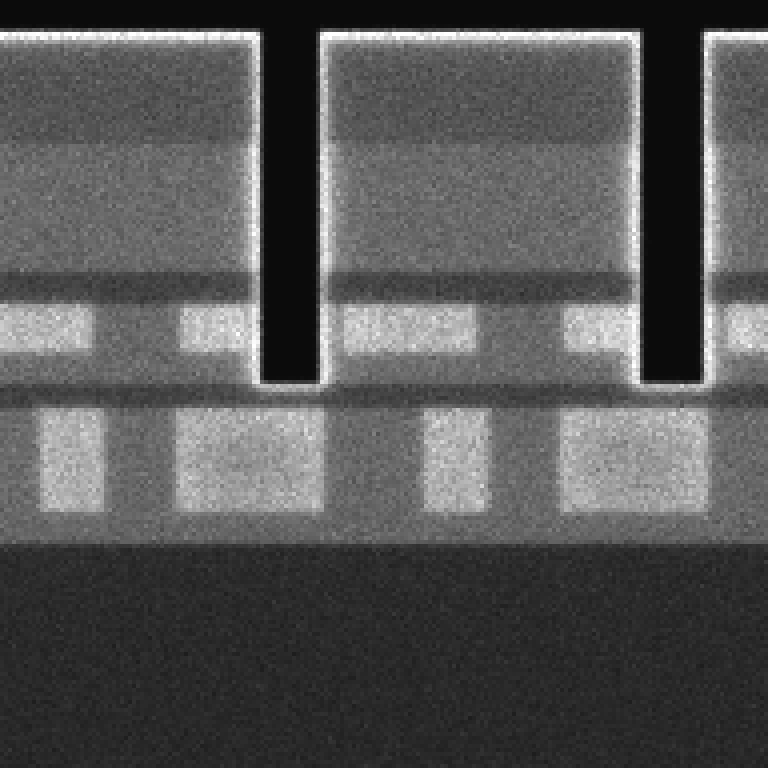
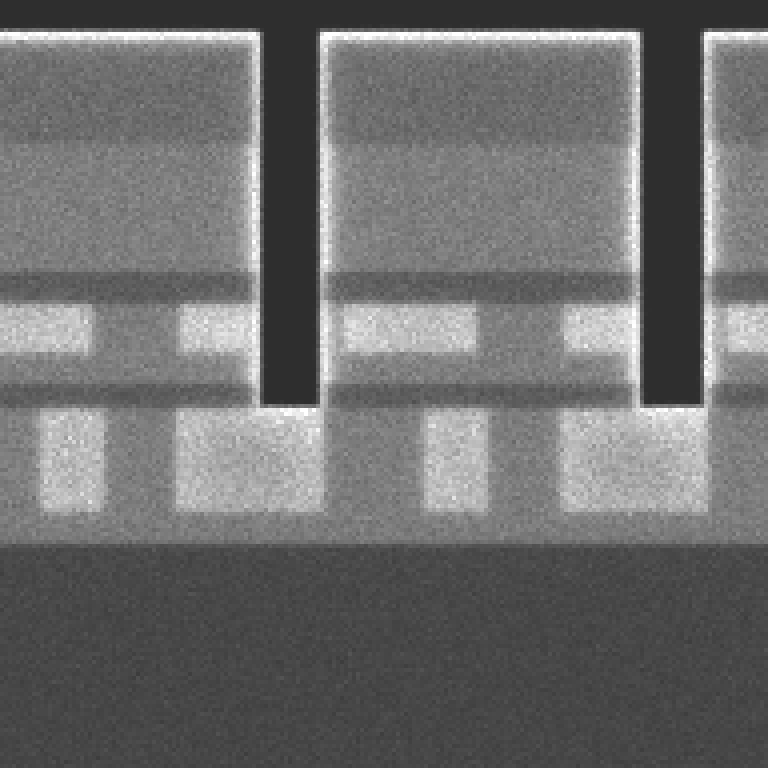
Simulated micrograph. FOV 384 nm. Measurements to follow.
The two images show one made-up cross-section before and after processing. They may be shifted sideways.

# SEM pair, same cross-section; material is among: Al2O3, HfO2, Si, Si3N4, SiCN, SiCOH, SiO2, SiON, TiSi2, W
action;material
removed;SiCN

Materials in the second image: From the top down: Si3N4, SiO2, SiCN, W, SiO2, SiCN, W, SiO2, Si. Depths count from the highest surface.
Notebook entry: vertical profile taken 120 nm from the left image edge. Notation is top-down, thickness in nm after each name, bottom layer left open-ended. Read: Si3N4 56, SiO2 64, SiCN 16, W 24, SiO2 16, SiCN 12, W 52, SiO2 16, Si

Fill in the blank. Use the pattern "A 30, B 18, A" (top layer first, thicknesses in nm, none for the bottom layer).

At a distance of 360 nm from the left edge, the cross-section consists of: Si3N4 56, SiO2 64, SiCN 16, SiO2 40, SiCN 12, SiO2 68, Si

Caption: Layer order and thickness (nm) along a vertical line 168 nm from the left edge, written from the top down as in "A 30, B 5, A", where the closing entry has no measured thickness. Si3N4 56, SiO2 64, SiCN 16, SiO2 40, SiCN 12, SiO2 68, Si